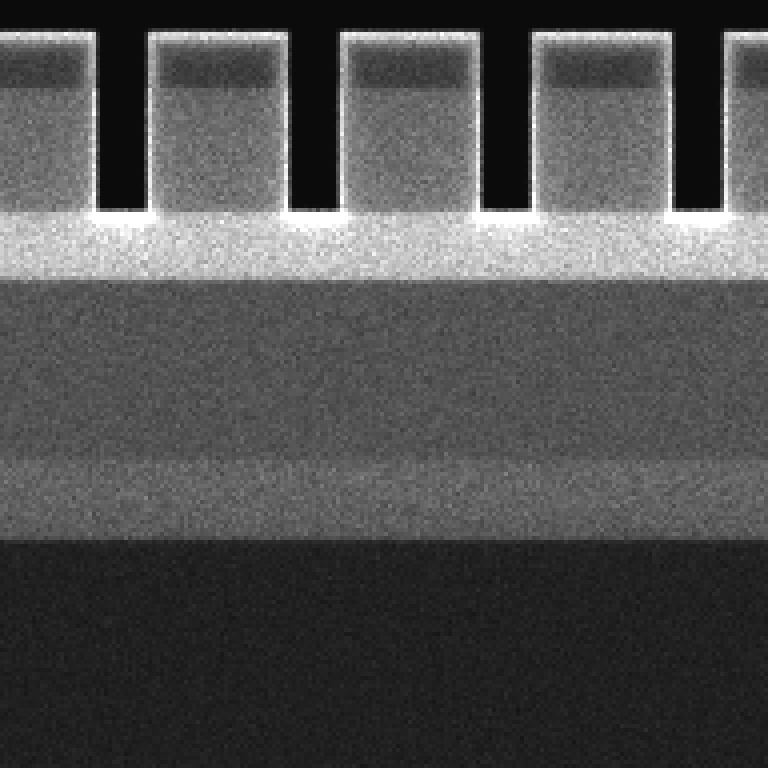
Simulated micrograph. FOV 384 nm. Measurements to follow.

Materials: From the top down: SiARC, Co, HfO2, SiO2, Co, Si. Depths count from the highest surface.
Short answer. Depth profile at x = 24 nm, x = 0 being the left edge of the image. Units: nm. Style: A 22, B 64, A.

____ SiARC 28, Co 62, HfO2 34, SiO2 90, Co 40, Si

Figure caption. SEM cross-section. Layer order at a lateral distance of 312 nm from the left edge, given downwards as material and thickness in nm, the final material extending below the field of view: SiARC 28, Co 62, HfO2 34, SiO2 90, Co 40, Si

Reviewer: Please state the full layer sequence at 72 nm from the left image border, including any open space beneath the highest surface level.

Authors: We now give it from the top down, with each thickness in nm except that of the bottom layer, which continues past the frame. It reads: empty 90, HfO2 34, SiO2 90, Co 40, Si